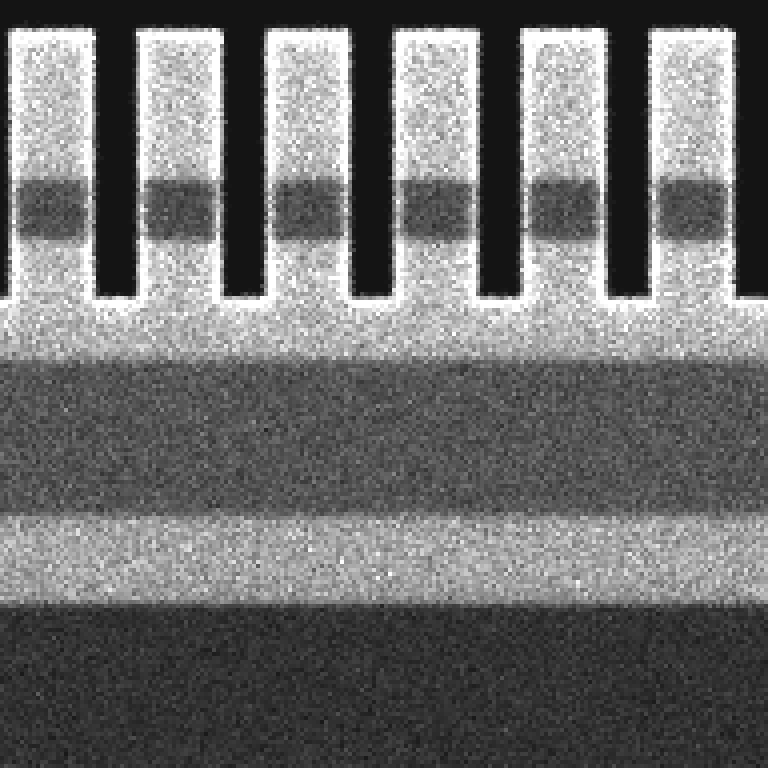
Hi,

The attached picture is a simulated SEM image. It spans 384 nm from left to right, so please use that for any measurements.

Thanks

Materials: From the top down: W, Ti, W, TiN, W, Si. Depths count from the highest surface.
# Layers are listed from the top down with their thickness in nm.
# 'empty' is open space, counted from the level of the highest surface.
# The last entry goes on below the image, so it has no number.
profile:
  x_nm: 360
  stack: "W 74, Ti 30, W 60, TiN 78, W 44, Si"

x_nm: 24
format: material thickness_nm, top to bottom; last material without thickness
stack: W 74, Ti 30, W 60, TiN 78, W 44, Si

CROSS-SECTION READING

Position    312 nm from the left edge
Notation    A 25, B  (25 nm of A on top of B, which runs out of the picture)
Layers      empty 134, W 30, TiN 78, W 44, Si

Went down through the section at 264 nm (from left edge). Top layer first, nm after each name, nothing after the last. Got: W 74, Ti 30, W 60, TiN 78, W 44, Si